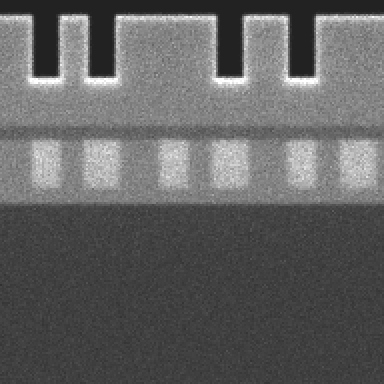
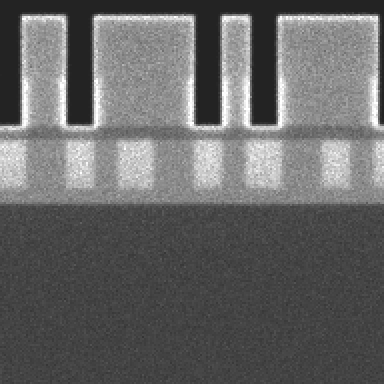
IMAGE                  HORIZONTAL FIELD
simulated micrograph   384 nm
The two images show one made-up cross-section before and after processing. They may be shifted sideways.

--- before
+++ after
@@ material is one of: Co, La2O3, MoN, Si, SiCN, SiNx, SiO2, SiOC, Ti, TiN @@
SiO2 removed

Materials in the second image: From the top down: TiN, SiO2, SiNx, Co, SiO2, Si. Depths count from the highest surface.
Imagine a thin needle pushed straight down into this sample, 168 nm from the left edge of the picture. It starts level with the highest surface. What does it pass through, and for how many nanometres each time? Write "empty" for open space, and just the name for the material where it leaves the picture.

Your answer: TiN 62, SiO2 48, SiNx 14, SiO2 64, Si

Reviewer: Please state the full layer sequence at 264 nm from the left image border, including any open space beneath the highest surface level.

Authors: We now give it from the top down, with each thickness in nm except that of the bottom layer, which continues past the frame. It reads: empty 110, SiNx 14, Co 48, SiO2 16, Si